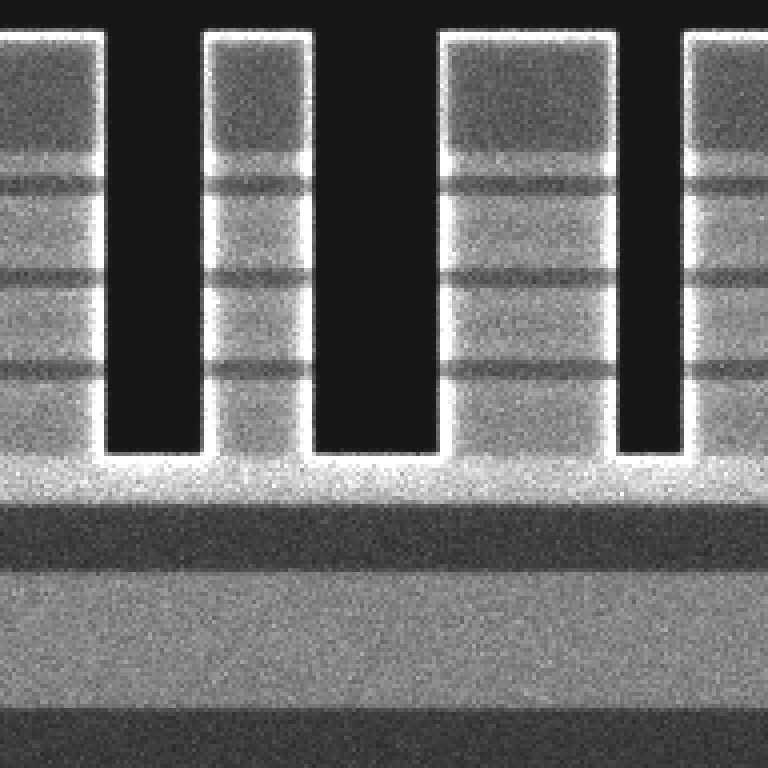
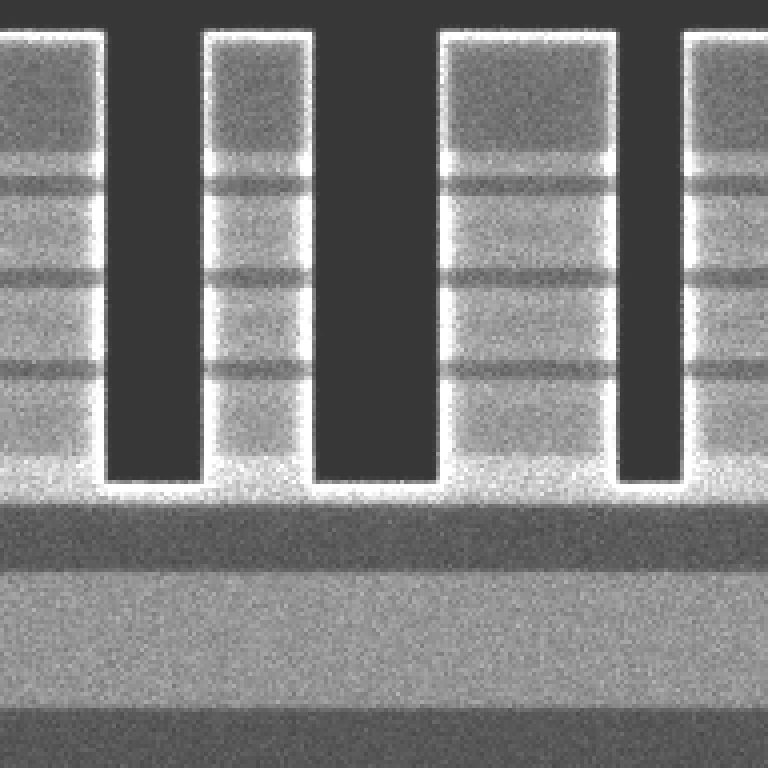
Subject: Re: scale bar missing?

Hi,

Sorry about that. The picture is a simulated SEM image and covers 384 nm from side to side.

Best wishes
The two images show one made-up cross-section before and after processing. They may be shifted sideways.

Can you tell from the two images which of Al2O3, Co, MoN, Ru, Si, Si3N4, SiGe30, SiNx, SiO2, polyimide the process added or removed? Yes, it removed Co.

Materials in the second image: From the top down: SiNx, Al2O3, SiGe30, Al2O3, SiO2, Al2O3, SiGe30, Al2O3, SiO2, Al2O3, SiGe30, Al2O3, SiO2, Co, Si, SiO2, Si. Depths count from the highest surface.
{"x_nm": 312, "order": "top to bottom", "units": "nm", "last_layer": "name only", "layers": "empty 226, Co 10, Si 34, SiO2 68, Si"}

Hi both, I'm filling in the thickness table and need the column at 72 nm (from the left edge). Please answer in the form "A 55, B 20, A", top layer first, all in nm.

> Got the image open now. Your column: empty 226, Co 10, Si 34, SiO2 68, Si